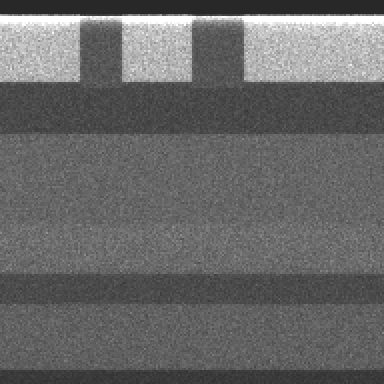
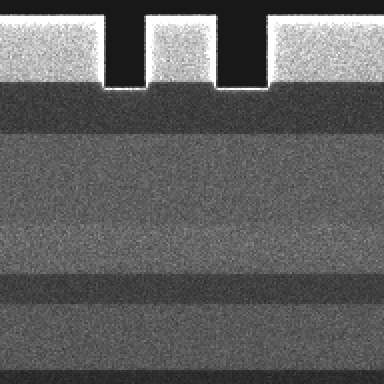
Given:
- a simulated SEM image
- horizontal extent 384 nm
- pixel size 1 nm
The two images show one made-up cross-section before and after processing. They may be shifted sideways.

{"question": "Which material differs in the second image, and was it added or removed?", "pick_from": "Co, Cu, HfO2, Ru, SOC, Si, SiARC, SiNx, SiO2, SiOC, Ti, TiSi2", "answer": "SOC, removed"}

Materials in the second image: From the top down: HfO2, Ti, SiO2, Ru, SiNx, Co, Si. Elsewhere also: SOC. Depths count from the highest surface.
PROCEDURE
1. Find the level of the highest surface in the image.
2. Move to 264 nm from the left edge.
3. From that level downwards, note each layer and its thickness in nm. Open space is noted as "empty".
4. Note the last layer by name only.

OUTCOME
empty 72, Ti 46, SiO2 90, Ru 50, SiNx 30, Co 66, Si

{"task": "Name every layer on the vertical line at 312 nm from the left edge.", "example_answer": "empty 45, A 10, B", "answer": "HfO2 66, Ti 52, SiO2 90, Ru 50, SiNx 30, Co 66, Si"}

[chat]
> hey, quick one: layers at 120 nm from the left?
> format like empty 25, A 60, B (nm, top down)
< empty 72, Ti 46, SiO2 90, Ru 50, SiNx 30, Co 66, Si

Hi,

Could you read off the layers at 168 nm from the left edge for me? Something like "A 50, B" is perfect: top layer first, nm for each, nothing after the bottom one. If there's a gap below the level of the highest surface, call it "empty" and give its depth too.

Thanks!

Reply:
HfO2 66, Ti 52, SiO2 90, Ru 50, SiNx 30, Co 66, Si